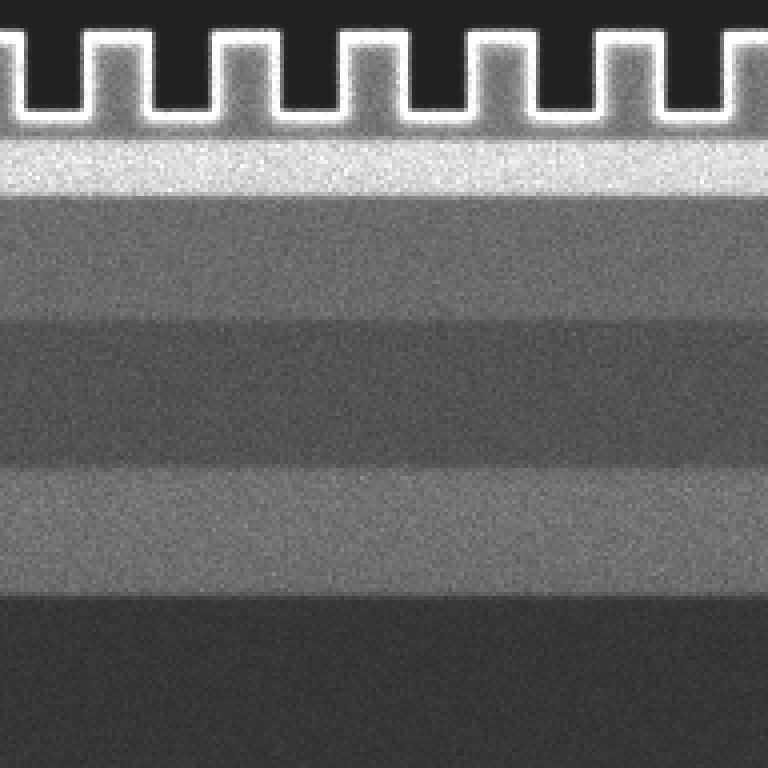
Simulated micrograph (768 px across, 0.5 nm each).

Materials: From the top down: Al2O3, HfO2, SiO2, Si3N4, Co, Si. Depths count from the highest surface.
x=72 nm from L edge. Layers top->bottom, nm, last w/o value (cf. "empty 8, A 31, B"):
Al2O3 54, HfO2 28, SiO2 62, Si3N4 74, Co 64, Si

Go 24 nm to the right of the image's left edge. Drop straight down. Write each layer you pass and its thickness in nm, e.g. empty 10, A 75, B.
empty 40, Al2O3 14, HfO2 28, SiO2 62, Si3N4 74, Co 64, Si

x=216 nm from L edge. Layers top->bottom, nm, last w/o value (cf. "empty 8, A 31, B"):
empty 40, Al2O3 14, HfO2 28, SiO2 62, Si3N4 74, Co 64, Si